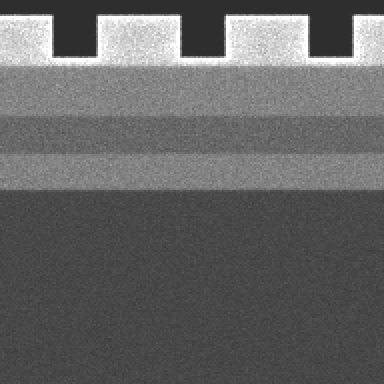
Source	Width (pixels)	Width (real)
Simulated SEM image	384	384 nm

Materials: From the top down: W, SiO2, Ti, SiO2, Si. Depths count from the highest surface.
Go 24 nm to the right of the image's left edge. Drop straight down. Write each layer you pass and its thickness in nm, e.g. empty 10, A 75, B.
W 50, SiO2 50, Ti 38, SiO2 36, Si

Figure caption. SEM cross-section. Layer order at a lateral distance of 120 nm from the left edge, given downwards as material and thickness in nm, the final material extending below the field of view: W 50, SiO2 50, Ti 38, SiO2 36, Si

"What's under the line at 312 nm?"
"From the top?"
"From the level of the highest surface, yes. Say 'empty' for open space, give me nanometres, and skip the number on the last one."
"empty 42, W 8, SiO2 50, Ti 38, SiO2 36, Si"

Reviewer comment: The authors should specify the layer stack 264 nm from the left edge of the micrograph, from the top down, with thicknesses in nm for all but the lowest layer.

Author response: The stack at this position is W 50, SiO2 50, Ti 38, SiO2 36, Si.